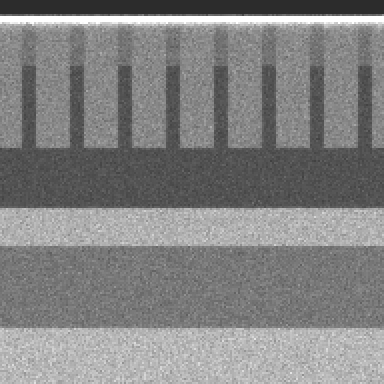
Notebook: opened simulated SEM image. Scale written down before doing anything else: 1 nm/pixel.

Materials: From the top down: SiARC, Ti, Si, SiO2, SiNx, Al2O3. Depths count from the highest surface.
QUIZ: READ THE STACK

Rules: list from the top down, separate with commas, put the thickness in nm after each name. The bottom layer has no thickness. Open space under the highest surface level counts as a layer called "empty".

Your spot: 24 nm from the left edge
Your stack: SiARC 8, Ti 42, Si 142, SiO2 38, SiNx 82, Al2O3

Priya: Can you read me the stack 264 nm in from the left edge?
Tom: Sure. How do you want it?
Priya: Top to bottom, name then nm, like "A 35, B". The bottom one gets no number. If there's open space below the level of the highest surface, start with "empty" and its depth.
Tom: SiARC 8, Ti 42, Si 142, SiO2 38, SiNx 82, Al2O3